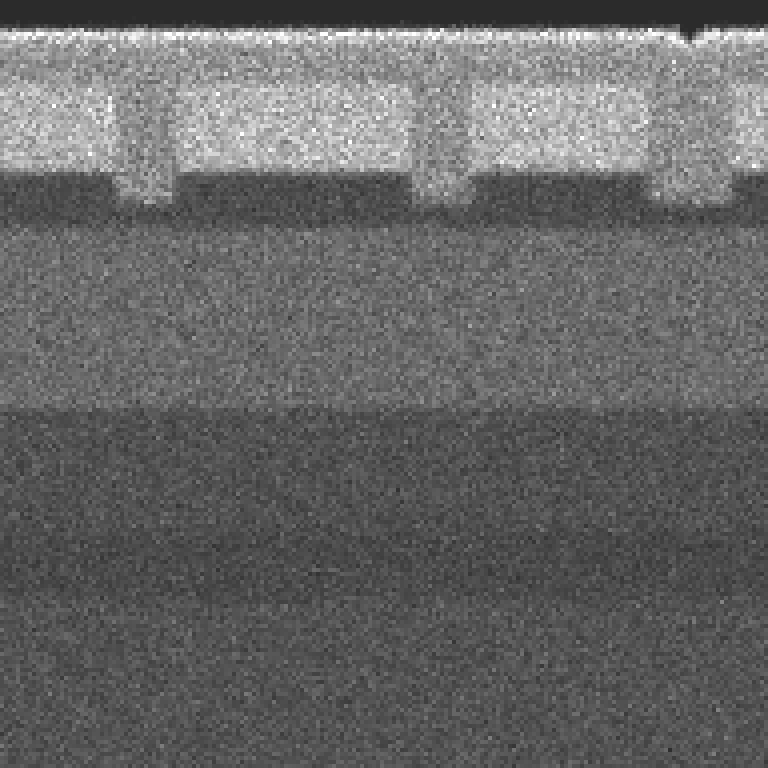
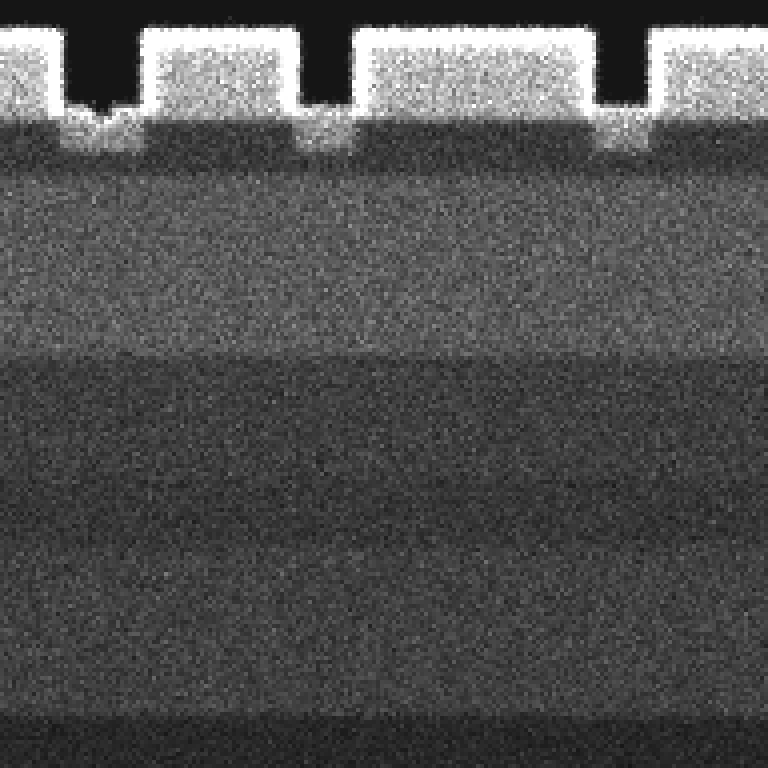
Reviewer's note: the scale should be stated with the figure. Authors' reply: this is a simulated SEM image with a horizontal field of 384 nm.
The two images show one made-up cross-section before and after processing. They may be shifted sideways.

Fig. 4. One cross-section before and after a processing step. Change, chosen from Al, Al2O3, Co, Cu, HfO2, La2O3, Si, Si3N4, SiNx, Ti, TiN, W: W removed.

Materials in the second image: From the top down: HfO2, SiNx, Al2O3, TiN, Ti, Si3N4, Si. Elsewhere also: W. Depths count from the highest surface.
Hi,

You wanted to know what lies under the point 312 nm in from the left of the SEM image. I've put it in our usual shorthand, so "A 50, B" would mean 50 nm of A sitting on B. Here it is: empty 38, W 22, SiNx 12, Al2O3 90, TiN 62, Ti 34, Si3N4 84, Si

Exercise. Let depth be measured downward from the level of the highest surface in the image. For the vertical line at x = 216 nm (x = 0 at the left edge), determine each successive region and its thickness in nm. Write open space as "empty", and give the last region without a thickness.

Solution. HfO2 44, SiNx 28, Al2O3 90, TiN 62, Ti 34, Si3N4 84, Si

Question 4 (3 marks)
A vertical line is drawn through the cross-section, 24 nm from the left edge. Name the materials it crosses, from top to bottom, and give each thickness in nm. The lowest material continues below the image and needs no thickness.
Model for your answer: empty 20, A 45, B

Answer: HfO2 44, SiNx 28, Al2O3 90, TiN 62, Ti 34, Si3N4 84, Si